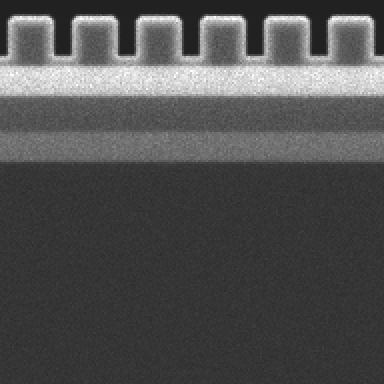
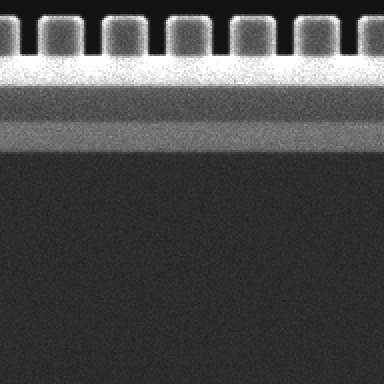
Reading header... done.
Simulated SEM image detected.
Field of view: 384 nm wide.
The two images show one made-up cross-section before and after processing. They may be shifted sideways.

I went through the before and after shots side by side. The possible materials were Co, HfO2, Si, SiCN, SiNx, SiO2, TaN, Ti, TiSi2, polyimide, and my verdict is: removed, SiO2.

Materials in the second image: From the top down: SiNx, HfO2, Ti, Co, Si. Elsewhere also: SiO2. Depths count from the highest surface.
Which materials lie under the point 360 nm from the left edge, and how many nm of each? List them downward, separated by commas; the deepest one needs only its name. empty 2, SiO2 38, HfO2 30, Ti 36, Co 30, Si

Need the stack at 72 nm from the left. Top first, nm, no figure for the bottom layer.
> SiNx 40, HfO2 30, Ti 36, Co 30, Si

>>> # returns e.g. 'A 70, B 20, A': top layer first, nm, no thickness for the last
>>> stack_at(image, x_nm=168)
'empty 2, SiO2 38, HfO2 30, Ti 36, Co 30, Si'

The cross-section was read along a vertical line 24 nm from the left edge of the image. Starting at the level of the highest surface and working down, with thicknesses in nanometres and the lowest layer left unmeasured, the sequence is empty 40, HfO2 30, Ti 36, Co 30, Si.